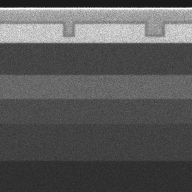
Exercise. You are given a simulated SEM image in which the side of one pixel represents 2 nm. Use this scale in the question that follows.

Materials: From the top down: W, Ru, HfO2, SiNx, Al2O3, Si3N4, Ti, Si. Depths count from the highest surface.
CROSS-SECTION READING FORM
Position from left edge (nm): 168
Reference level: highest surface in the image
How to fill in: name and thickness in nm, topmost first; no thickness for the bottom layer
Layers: W 26, Ru 6, HfO2 38, SiNx 64, Al2O3 48, Si3N4 50, Ti 74, Si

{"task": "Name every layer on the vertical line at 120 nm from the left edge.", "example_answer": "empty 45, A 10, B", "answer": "W 26, Ru 6, HfO2 38, SiNx 64, Al2O3 48, Si3N4 50, Ti 74, Si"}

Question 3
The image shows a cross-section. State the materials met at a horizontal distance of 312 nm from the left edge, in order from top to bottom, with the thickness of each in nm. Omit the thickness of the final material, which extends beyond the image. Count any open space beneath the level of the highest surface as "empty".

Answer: W 52, Ru 6, HfO2 12, SiNx 64, Al2O3 48, Si3N4 50, Ti 74, Si